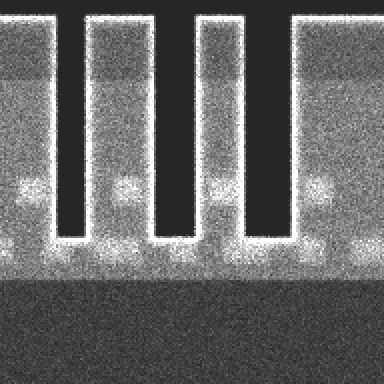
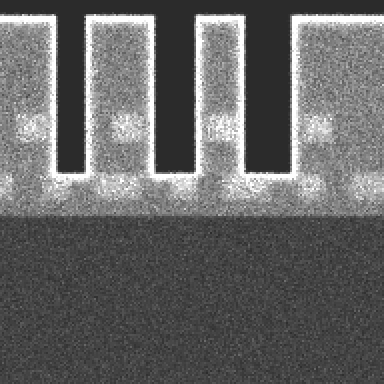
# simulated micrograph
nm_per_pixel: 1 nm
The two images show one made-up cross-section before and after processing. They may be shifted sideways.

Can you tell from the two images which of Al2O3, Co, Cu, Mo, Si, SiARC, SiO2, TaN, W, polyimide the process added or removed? Yes, it removed SiARC.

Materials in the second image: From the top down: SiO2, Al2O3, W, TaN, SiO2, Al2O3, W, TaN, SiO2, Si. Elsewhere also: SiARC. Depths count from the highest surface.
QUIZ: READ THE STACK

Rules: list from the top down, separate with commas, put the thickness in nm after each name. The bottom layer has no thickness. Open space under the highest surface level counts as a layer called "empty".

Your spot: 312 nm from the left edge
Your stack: SiO2 86, Al2O3 12, W 22, TaN 6, SiO2 18, Al2O3 14, W 20, TaN 6, SiO2 16, Si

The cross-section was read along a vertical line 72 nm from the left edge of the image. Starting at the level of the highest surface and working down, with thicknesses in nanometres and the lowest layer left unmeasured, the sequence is empty 158, SiO2 42, Si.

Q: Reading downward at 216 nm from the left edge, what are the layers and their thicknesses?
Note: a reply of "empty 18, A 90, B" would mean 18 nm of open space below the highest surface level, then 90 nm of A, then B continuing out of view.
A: SiO2 86, Al2O3 12, W 22, TaN 6, SiO2 18, Al2O3 14, SiO2 42, Si